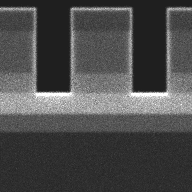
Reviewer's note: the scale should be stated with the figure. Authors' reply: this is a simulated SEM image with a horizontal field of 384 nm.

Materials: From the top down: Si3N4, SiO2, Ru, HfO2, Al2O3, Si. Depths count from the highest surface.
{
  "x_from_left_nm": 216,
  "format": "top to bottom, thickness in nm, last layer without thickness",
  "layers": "Si3N4 46, SiO2 84, Ru 40, HfO2 42, Al2O3 36, Si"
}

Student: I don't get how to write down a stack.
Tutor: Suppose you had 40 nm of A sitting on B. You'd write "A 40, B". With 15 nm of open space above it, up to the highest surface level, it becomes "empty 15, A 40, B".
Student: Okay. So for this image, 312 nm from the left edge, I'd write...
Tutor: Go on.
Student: empty 170, HfO2 42, Al2O3 36, Si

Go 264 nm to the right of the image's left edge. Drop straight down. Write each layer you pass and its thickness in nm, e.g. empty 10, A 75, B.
empty 170, HfO2 42, Al2O3 36, Si